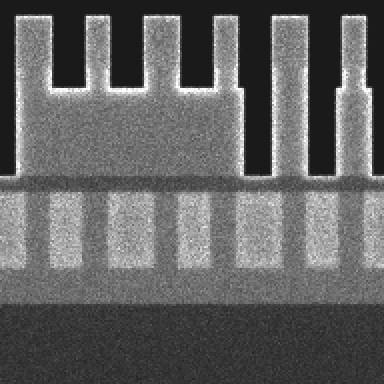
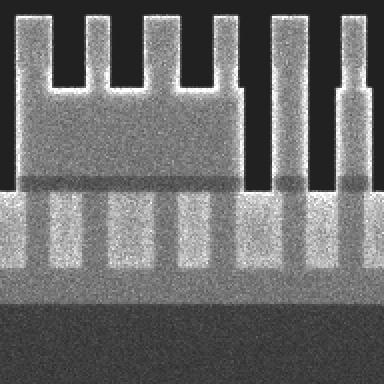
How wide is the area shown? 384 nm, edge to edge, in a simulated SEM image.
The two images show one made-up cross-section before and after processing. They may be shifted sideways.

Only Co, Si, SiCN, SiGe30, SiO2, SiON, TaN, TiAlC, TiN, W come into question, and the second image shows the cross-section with SiCN removed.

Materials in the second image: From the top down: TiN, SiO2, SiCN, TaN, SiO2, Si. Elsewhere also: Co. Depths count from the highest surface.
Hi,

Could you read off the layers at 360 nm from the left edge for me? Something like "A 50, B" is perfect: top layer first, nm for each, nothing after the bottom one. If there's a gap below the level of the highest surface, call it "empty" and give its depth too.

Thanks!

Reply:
TiN 52, SiO2 108, SiCN 16, SiO2 112, Si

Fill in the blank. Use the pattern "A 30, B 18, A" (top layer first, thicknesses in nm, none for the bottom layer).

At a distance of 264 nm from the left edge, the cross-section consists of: empty 176, Co 66, TaN 10, SiO2 36, Si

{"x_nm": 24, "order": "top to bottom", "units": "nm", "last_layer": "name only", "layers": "TiN 52, SiO2 108, SiCN 16, TaN 76, SiO2 36, Si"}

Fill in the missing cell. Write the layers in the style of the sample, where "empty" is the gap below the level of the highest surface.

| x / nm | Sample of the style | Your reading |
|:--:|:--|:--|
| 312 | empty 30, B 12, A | empty 176, TaN 76, SiO2 36, Si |